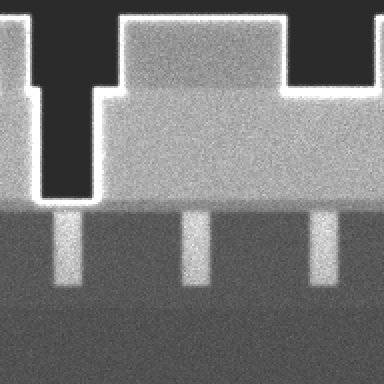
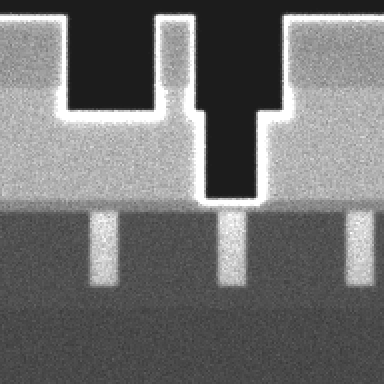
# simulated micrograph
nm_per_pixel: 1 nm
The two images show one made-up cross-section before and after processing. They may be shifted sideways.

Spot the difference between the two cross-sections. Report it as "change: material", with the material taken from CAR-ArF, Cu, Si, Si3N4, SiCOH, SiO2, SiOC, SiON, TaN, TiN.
removed: SiO2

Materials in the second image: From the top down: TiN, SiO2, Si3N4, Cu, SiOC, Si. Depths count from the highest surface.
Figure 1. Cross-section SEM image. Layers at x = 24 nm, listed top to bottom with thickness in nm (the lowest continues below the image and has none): TiN 72, SiO2 112, Si3N4 12, SiOC 96, Si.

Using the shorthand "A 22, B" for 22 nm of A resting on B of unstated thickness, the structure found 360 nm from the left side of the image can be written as TiN 72, SiO2 112, Si3N4 12, Cu 74, SiOC 22, Si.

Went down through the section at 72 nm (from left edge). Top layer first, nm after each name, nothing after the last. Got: empty 96, SiO2 88, Si3N4 12, SiOC 96, Si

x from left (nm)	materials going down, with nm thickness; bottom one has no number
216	empty 184, Si3N4 12, SiOC 96, Si